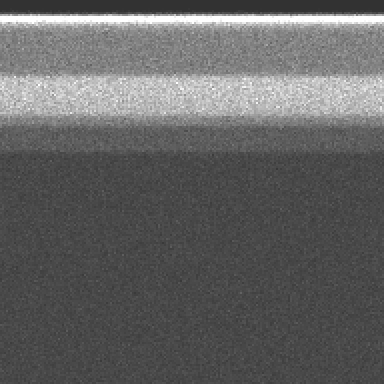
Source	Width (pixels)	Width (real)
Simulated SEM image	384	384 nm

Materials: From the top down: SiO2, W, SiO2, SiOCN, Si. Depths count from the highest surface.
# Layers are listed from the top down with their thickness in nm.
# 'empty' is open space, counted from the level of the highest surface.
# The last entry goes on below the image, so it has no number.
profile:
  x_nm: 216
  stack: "SiO2 60, W 40, SiO2 10, SiOCN 26, Si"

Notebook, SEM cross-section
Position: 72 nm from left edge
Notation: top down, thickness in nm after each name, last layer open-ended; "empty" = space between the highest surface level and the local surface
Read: SiO2 60, W 40, SiO2 10, SiOCN 26, Si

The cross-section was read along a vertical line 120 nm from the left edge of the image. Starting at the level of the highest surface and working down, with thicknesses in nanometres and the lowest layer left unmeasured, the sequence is SiO2 60, W 40, SiO2 10, SiOCN 26, Si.